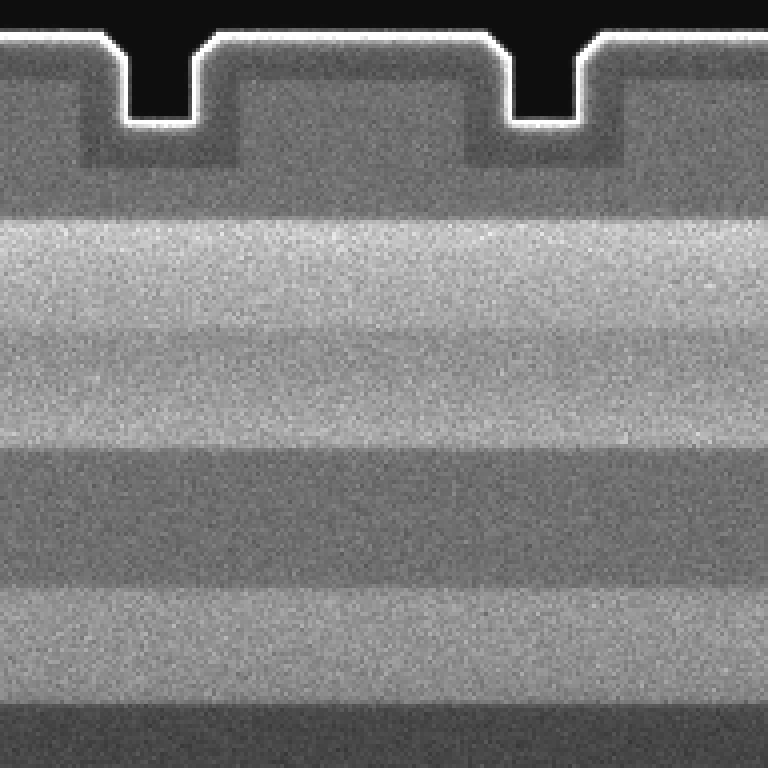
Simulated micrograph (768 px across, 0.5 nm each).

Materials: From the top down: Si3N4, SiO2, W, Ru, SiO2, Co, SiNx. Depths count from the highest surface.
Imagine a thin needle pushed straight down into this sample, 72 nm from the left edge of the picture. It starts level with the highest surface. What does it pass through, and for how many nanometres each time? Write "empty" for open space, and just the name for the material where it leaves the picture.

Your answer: empty 44, Si3N4 24, SiO2 26, W 54, Ru 60, SiO2 70, Co 58, SiNx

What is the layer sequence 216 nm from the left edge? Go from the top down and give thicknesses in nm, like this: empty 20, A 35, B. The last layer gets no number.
Si3N4 24, SiO2 70, W 54, Ru 60, SiO2 70, Co 58, SiNx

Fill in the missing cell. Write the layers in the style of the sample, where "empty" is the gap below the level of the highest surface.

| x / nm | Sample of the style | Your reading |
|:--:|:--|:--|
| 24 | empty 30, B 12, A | Si3N4 24, SiO2 70, W 54, Ru 60, SiO2 70, Co 58, SiNx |